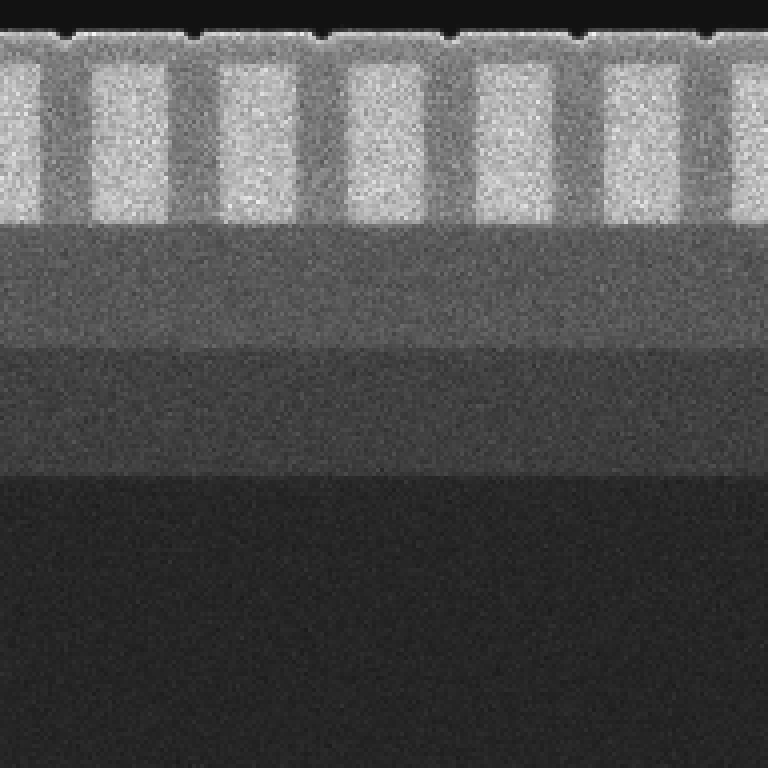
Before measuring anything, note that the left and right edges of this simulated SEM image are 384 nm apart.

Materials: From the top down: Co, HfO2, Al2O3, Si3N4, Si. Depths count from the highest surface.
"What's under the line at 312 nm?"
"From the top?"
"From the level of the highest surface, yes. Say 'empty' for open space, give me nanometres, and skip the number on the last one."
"Co 16, HfO2 80, Al2O3 62, Si3N4 64, Si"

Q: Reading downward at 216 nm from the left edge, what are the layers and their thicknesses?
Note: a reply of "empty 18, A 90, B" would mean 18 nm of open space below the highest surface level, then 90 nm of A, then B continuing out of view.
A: Co 96, Al2O3 62, Si3N4 64, Si